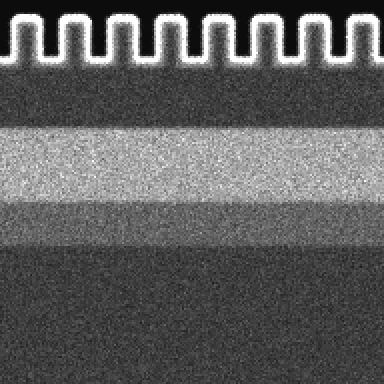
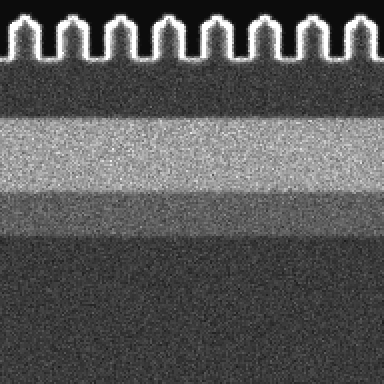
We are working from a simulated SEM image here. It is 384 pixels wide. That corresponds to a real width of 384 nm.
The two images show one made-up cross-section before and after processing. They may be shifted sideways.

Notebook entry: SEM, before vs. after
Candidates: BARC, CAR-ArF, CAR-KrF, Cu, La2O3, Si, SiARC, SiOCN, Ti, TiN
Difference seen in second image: SiOCN removed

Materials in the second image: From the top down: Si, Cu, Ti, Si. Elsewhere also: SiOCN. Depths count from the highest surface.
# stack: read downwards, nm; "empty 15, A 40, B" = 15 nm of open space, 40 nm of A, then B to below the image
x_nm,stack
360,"Si 102, Cu 74, Ti 44, Si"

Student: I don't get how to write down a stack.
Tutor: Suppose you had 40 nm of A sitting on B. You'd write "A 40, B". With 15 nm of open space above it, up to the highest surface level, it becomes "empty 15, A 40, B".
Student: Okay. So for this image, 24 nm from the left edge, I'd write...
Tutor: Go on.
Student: Si 102, Cu 74, Ti 44, Si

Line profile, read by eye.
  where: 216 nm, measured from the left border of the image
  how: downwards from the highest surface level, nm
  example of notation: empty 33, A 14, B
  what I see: Si 102, Cu 74, Ti 44, Si